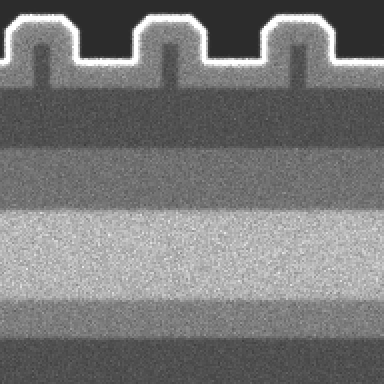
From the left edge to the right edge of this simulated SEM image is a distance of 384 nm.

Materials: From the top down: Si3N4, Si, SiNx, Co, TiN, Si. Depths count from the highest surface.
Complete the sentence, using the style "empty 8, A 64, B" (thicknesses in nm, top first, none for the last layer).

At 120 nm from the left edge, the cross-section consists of empty 44, Si3N4 28, Si 60, SiNx 62, Co 90, TiN 38, Si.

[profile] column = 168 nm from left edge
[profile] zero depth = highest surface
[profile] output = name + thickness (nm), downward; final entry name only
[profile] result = Si3N4 28, Si 104, SiNx 62, Co 90, TiN 38, Si